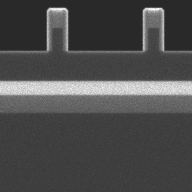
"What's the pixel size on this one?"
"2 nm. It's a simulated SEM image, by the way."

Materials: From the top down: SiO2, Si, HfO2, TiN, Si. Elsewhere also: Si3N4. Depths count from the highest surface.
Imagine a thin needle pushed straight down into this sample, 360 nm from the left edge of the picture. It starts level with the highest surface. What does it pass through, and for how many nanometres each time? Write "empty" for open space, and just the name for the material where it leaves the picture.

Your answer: empty 86, Si 60, HfO2 28, TiN 36, Si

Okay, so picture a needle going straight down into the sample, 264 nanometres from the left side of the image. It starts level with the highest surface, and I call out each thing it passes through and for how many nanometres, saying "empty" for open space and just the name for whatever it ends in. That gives empty 86, Si 60, HfO2 28, TiN 36, Si